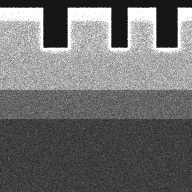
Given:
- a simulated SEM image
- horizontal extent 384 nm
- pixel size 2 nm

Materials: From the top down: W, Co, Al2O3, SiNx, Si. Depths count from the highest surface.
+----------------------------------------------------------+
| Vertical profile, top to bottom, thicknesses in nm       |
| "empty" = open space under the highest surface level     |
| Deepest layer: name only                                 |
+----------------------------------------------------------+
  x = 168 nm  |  W 26, Co 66, Al2O3 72, SiNx 58, Si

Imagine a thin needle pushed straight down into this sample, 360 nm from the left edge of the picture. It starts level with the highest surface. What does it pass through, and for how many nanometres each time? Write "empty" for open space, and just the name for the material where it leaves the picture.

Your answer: W 26, Co 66, Al2O3 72, SiNx 58, Si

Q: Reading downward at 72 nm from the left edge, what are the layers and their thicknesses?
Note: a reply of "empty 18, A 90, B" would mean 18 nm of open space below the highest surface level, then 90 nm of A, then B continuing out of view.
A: W 26, Co 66, Al2O3 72, SiNx 58, Si